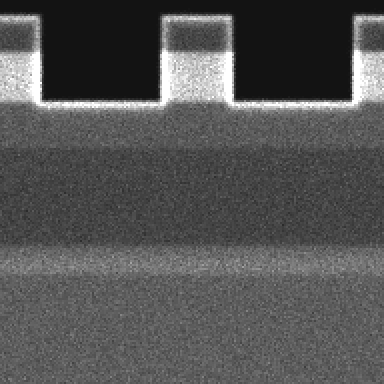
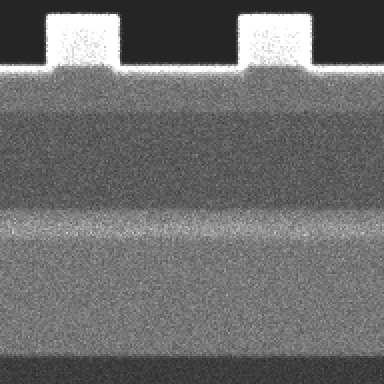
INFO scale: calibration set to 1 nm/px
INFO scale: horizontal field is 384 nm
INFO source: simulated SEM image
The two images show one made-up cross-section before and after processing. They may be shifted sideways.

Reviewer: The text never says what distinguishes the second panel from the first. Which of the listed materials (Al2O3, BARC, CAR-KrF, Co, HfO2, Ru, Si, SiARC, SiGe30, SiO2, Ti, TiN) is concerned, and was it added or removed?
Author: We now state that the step removed SiARC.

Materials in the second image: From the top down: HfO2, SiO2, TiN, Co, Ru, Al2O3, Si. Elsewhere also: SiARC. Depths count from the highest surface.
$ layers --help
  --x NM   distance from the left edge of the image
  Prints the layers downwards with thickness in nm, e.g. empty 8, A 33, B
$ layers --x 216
empty 50, SiO2 46, TiN 98, Co 12, Ru 16, Al2O3 118, Si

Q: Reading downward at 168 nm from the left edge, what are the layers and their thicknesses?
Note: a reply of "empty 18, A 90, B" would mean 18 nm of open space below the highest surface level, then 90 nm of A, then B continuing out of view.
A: empty 50, SiO2 46, TiN 98, Co 12, Ru 16, Al2O3 118, Si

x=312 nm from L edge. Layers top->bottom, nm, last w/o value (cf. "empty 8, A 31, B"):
empty 50, SiO2 46, TiN 98, Co 12, Ru 16, Al2O3 118, Si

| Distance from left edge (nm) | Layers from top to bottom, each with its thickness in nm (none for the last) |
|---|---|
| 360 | empty 50, SiO2 46, TiN 98, Co 12, Ru 16, Al2O3 118, Si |